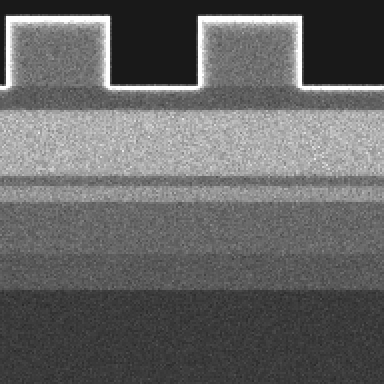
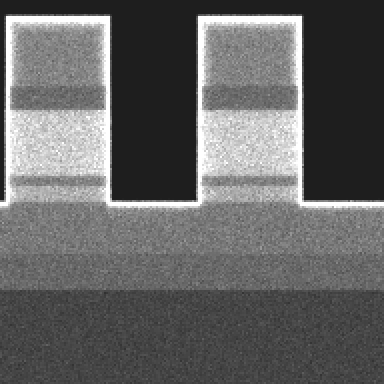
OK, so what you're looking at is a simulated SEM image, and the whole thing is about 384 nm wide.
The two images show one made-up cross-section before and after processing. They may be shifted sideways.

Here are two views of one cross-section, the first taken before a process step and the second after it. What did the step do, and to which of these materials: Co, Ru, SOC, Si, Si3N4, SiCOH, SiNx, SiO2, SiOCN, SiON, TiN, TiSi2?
It removed Co and Ru and SiNx and TiN.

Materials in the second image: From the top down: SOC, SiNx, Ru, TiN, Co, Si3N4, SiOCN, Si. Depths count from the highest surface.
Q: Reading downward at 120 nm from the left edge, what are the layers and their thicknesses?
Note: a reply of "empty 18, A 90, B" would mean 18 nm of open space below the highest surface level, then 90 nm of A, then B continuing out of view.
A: empty 186, Si3N4 52, SiOCN 36, Si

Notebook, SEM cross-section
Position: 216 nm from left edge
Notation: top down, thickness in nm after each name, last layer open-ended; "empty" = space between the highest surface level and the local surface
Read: SOC 70, SiNx 24, Ru 66, TiN 10, Co 16, Si3N4 52, SiOCN 36, Si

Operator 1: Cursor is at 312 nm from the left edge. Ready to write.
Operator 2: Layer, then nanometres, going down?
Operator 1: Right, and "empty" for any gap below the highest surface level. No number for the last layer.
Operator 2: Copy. empty 186, Si3N4 52, SiOCN 36, Si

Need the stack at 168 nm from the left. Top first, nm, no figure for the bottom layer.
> empty 186, Si3N4 52, SiOCN 36, Si